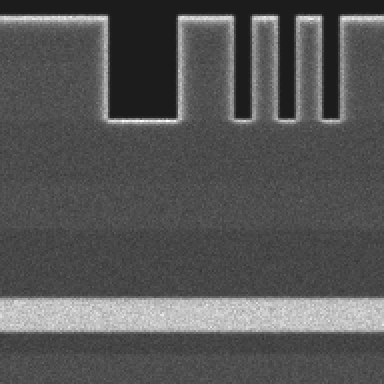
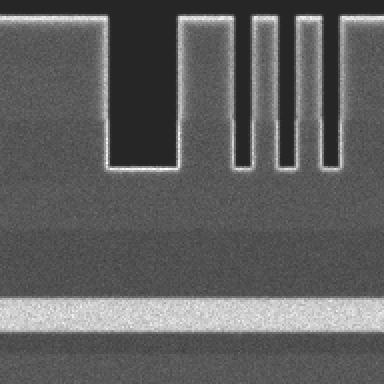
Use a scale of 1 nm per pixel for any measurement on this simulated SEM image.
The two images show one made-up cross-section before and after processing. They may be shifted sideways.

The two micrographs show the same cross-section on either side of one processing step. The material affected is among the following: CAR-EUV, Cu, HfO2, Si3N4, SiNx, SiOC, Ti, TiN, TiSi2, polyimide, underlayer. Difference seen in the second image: TiN removed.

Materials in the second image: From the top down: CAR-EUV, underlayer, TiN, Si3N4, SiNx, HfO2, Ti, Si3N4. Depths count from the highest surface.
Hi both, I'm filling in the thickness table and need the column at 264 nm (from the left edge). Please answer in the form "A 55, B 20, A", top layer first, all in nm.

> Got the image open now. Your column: CAR-EUV 48, underlayer 56, TiN 62, Si3N4 48, SiNx 68, HfO2 34, Ti 22, Si3N4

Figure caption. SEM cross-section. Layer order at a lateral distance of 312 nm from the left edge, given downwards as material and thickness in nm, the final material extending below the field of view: CAR-EUV 48, underlayer 56, TiN 62, Si3N4 48, SiNx 68, HfO2 34, Ti 22, Si3N4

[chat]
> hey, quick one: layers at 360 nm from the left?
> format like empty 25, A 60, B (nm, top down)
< CAR-EUV 48, underlayer 56, TiN 62, Si3N4 48, SiNx 68, HfO2 34, Ti 22, Si3N4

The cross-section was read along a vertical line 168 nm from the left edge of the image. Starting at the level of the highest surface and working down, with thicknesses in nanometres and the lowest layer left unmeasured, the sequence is empty 152, TiN 14, Si3N4 48, SiNx 68, HfO2 34, Ti 22, Si3N4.